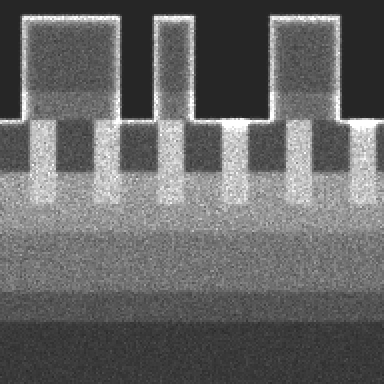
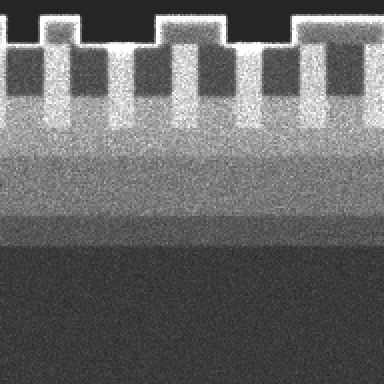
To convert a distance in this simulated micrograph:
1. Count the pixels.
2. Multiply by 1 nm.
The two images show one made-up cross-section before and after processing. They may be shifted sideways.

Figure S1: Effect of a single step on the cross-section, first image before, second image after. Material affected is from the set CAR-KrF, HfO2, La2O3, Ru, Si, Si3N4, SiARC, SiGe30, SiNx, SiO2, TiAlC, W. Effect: removed SiARC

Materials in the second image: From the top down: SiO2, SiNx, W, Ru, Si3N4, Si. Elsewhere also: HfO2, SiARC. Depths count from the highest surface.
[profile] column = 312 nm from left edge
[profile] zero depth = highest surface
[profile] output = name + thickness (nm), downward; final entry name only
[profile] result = SiO2 28, HfO2 84, W 28, Ru 60, Si3N4 30, Si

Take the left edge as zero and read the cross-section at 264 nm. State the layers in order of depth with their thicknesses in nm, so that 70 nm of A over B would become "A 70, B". empty 28, SiNx 52, W 60, Ru 60, Si3N4 30, Si